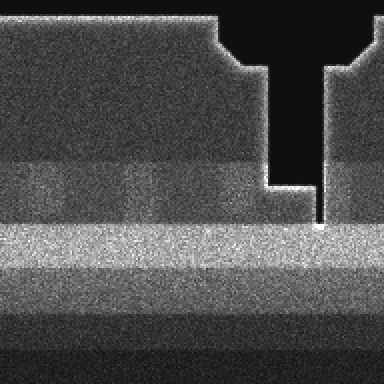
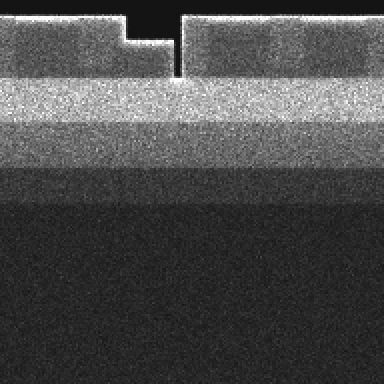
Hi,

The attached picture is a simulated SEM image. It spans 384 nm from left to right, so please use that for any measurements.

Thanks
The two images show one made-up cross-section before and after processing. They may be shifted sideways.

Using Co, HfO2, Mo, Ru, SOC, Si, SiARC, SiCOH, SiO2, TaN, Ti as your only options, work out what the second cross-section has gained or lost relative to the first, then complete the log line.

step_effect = removed SOC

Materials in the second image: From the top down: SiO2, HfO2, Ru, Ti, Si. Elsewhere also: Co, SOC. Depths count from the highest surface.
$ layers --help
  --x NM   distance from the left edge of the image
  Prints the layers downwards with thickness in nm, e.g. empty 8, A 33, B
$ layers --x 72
SiO2 62, HfO2 44, Ru 46, Ti 36, Si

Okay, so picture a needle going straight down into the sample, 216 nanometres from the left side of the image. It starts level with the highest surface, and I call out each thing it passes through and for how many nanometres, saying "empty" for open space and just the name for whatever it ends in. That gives SiO2 62, HfO2 44, Ru 46, Ti 36, Si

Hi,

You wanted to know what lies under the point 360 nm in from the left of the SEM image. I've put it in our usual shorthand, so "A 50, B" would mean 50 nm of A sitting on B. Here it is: SiO2 62, HfO2 44, Ru 46, Ti 36, Si